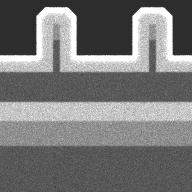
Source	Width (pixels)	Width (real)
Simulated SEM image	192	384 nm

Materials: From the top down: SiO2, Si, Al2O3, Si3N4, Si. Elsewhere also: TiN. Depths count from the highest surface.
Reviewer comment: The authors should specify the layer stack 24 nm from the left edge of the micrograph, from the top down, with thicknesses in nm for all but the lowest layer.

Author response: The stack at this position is empty 96, SiO2 32, Si 60, Al2O3 38, Si3N4 50, Si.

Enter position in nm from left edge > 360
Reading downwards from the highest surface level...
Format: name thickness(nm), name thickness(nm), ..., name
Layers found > empty 96, SiO2 32, Si 60, Al2O3 38, Si3N4 50, Si